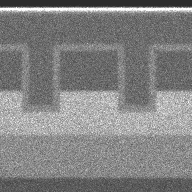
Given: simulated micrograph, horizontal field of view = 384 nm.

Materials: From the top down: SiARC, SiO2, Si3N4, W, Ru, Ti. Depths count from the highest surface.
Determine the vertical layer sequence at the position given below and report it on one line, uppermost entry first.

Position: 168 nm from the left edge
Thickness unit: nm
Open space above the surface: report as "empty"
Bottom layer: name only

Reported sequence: SiARC 72, SiO2 14, Si3N4 80, W 88, Ru 86, Ti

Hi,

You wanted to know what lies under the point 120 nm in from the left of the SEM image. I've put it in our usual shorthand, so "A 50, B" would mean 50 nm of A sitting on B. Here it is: SiARC 72, SiO2 14, Si3N4 80, W 88, Ru 86, Ti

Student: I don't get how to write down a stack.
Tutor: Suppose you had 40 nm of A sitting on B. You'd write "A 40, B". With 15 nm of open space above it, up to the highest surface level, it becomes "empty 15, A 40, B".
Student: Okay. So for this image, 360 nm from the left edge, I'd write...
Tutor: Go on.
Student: SiARC 72, SiO2 14, Si3N4 80, W 88, Ru 86, Ti